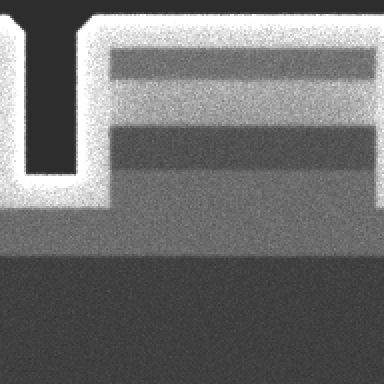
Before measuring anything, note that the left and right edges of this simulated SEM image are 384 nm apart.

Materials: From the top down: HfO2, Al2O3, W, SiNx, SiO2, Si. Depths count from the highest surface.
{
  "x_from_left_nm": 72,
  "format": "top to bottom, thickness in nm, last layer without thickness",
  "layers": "empty 160, HfO2 32, SiO2 48, Si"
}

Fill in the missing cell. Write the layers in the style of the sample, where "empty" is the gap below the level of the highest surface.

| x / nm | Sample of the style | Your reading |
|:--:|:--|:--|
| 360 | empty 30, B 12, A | HfO2 32, Al2O3 32, W 46, SiNx 44, SiO2 86, Si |